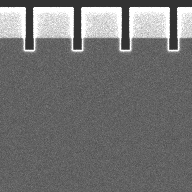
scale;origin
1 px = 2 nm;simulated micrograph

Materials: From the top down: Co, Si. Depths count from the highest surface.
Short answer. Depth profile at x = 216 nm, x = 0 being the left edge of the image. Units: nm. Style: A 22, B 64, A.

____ Co 60, Si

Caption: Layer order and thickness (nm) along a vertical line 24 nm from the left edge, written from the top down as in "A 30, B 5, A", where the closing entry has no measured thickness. Co 60, Si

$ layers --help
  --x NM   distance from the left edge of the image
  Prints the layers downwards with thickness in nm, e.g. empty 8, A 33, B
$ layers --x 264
Co 60, Si